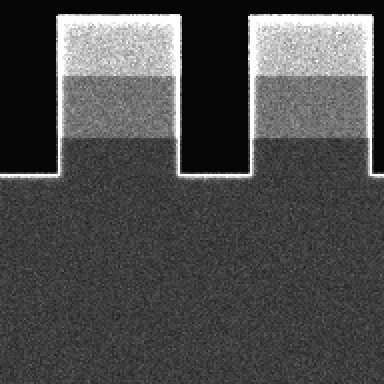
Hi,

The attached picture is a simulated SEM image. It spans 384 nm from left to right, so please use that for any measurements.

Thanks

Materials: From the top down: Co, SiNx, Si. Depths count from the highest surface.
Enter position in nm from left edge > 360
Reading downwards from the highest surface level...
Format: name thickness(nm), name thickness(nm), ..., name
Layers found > Co 60, SiNx 62, Si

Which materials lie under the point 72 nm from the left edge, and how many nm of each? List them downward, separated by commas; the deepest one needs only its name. Co 60, SiNx 62, Si